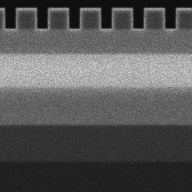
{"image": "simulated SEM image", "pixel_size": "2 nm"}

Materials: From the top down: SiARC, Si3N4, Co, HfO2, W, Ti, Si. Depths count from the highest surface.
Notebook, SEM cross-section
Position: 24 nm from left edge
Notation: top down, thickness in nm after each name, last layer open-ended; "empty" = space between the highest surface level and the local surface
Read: empty 42, Co 50, HfO2 66, W 76, Ti 74, Si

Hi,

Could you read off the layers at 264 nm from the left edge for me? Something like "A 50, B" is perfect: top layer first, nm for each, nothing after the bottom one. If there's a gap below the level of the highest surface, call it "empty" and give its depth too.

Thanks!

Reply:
SiARC 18, Si3N4 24, Co 50, HfO2 66, W 76, Ti 74, Si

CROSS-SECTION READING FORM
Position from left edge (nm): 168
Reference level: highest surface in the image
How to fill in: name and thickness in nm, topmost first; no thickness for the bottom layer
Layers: SiARC 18, Si3N4 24, Co 50, HfO2 66, W 76, Ti 74, Si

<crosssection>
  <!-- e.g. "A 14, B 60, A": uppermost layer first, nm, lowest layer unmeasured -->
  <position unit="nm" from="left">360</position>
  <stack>SiARC 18, Si3N4 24, Co 50, HfO2 66, W 76, Ti 74, Si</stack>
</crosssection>